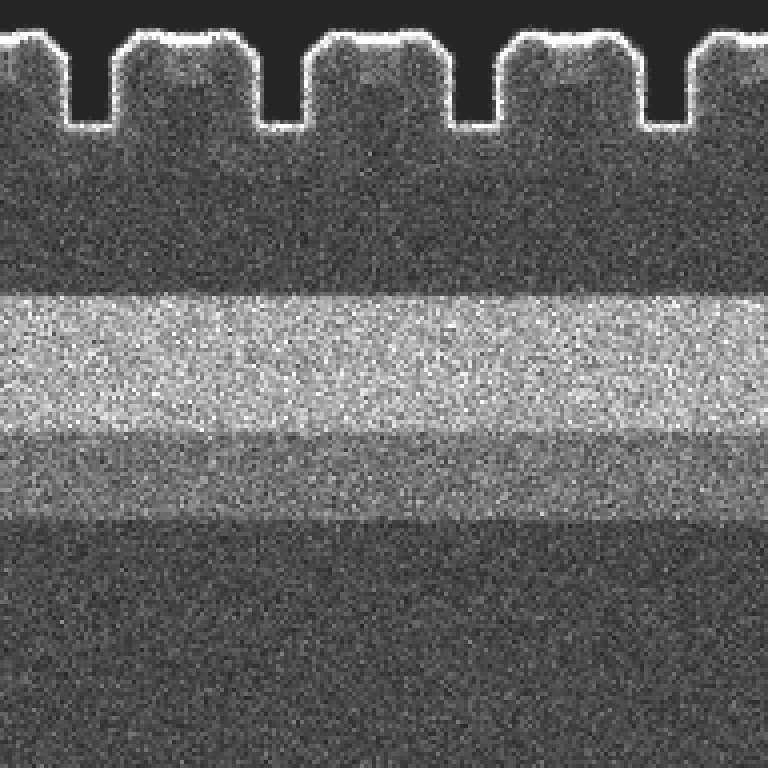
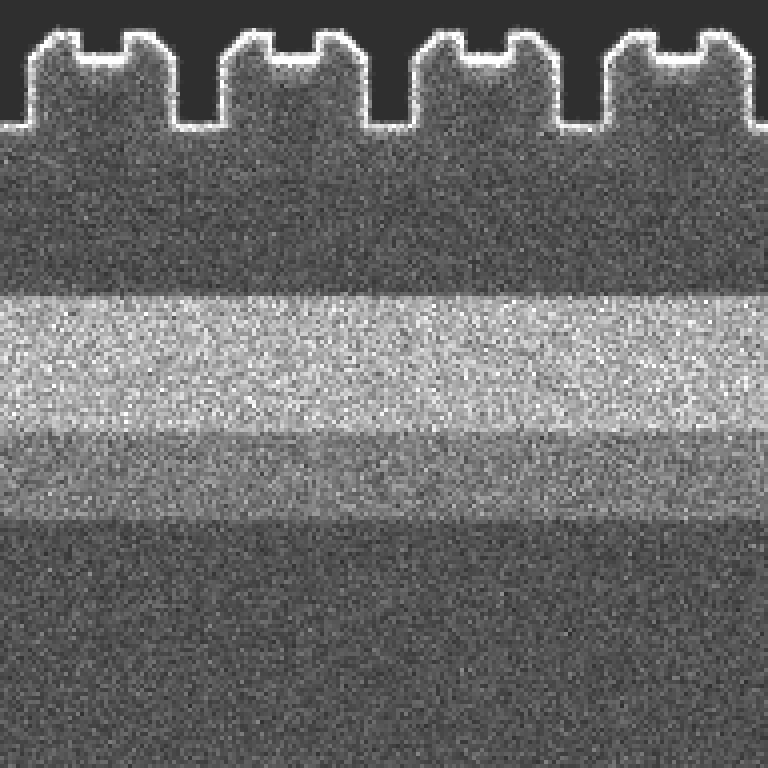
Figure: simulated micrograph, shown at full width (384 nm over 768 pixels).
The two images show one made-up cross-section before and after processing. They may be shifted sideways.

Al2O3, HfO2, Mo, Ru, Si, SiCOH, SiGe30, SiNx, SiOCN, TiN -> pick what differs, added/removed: SiNx removed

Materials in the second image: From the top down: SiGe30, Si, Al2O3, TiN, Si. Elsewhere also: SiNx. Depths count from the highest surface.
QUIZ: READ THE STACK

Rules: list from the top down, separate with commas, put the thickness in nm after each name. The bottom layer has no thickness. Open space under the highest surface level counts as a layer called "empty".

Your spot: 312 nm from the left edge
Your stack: empty 2, SiGe30 70, Si 60, Al2O3 68, TiN 44, Si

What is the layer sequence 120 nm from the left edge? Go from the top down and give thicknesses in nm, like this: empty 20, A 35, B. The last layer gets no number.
empty 2, SiGe30 70, Si 60, Al2O3 68, TiN 44, Si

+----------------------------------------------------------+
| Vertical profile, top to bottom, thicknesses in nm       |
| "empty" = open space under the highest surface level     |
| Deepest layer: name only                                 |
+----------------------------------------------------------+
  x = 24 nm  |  empty 2, SiGe30 70, Si 60, Al2O3 68, TiN 44, Si